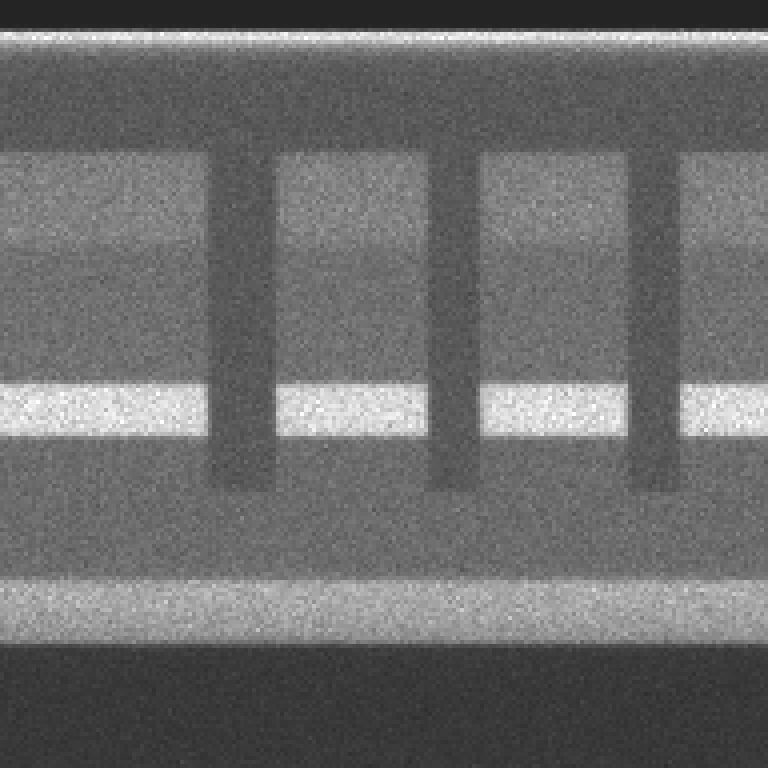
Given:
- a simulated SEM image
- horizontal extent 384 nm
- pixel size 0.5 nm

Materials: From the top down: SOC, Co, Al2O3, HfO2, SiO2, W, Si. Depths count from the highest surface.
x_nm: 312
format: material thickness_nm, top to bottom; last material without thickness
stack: SOC 60, Co 46, Al2O3 70, HfO2 26, SiO2 72, W 32, Si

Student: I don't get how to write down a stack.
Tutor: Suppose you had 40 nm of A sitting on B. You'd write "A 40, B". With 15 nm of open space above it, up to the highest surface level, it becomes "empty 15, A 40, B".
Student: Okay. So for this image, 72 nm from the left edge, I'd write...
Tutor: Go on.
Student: SOC 60, Co 46, Al2O3 70, HfO2 26, SiO2 72, W 32, Si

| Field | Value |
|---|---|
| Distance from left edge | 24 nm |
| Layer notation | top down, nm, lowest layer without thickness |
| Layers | SOC 60, Co 46, Al2O3 70, HfO2 26, SiO2 72, W 32, Si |